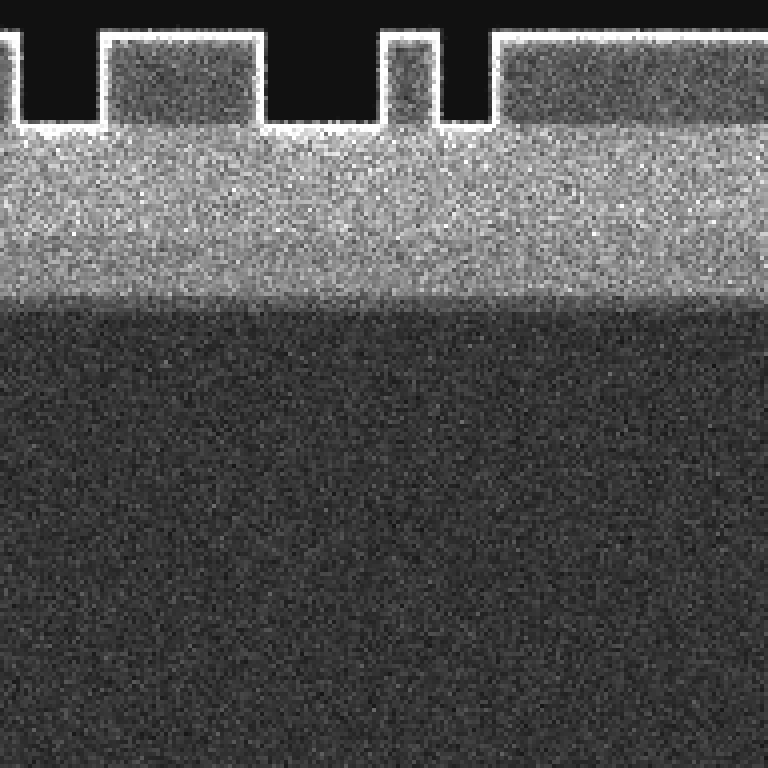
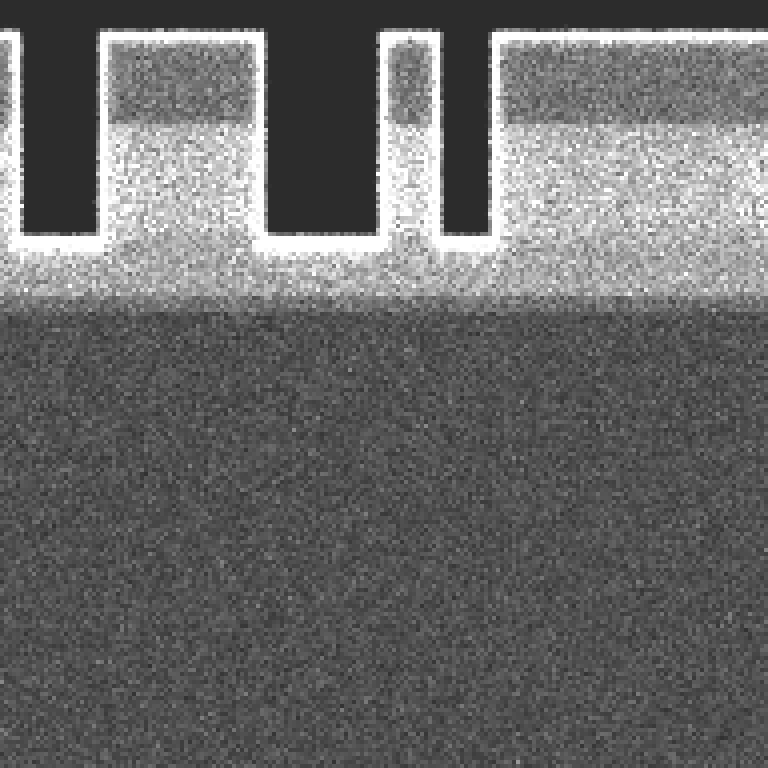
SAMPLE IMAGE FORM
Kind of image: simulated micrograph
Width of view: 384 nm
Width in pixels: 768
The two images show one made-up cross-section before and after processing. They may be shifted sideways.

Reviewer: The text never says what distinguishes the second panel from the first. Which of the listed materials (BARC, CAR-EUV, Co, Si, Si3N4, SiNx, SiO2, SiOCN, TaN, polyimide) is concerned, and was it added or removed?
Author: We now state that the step removed Co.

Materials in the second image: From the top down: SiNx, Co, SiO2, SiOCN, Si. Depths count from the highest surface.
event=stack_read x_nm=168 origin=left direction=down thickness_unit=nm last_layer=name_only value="empty 102, SiO2 30, SiOCN 8, Si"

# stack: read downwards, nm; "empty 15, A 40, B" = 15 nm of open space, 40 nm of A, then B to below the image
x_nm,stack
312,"SiNx 46, Co 56, SiO2 30, SiOCN 8, Si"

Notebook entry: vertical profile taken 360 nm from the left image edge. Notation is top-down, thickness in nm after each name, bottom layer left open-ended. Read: SiNx 46, Co 56, SiO2 30, SiOCN 8, Si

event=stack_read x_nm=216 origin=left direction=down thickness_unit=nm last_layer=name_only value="SiNx 46, Co 56, SiO2 30, SiOCN 8, Si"